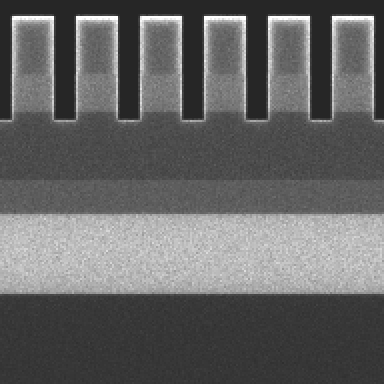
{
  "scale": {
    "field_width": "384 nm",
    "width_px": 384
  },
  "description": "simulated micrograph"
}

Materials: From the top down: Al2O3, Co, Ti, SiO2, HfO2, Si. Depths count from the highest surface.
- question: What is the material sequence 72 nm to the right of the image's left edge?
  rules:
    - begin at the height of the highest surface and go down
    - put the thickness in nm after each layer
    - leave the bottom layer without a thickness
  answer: empty 104, Ti 60, SiO2 34, HfO2 80, Si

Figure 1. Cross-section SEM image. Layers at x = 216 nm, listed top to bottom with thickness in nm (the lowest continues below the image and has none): Al2O3 58, Co 38, Ti 68, SiO2 34, HfO2 80, Si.